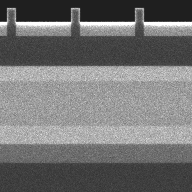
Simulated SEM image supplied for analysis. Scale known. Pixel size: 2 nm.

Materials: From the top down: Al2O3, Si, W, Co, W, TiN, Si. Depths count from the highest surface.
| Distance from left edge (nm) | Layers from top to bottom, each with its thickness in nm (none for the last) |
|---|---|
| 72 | empty 28, Al2O3 28, Si 60, W 30, Co 90, W 36, TiN 38, Si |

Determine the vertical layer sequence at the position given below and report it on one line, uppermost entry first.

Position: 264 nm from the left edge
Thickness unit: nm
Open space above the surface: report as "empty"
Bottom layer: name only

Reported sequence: empty 28, Al2O3 28, Si 60, W 30, Co 90, W 36, TiN 38, Si